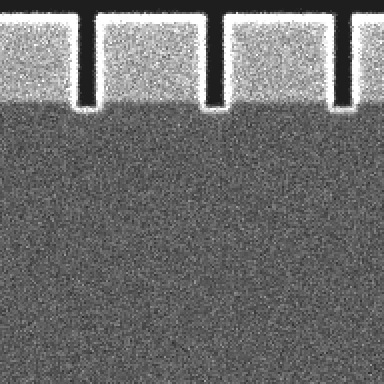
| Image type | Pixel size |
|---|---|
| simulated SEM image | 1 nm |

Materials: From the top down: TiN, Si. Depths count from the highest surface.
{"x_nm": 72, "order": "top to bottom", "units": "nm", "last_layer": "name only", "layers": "TiN 86, Si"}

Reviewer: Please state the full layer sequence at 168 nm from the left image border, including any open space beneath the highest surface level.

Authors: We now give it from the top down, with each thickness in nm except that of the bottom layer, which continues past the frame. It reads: TiN 86, Si